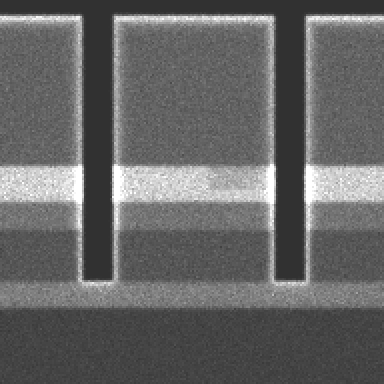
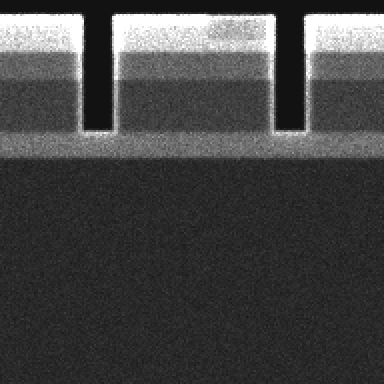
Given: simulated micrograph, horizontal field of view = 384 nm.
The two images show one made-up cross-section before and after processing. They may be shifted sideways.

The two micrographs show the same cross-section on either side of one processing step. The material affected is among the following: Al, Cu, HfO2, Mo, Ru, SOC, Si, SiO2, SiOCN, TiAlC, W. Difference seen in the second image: SOC removed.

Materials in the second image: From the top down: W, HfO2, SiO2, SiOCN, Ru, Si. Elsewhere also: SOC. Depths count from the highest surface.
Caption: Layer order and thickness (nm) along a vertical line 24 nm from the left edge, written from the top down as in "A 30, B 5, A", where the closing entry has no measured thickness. HfO2 36, SiO2 28, SiOCN 52, Ru 26, Si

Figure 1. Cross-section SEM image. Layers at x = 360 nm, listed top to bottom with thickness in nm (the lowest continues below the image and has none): HfO2 36, SiO2 28, SiOCN 52, Ru 26, Si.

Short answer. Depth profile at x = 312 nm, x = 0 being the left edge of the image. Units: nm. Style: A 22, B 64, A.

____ HfO2 36, SiO2 28, SiOCN 52, Ru 26, Si